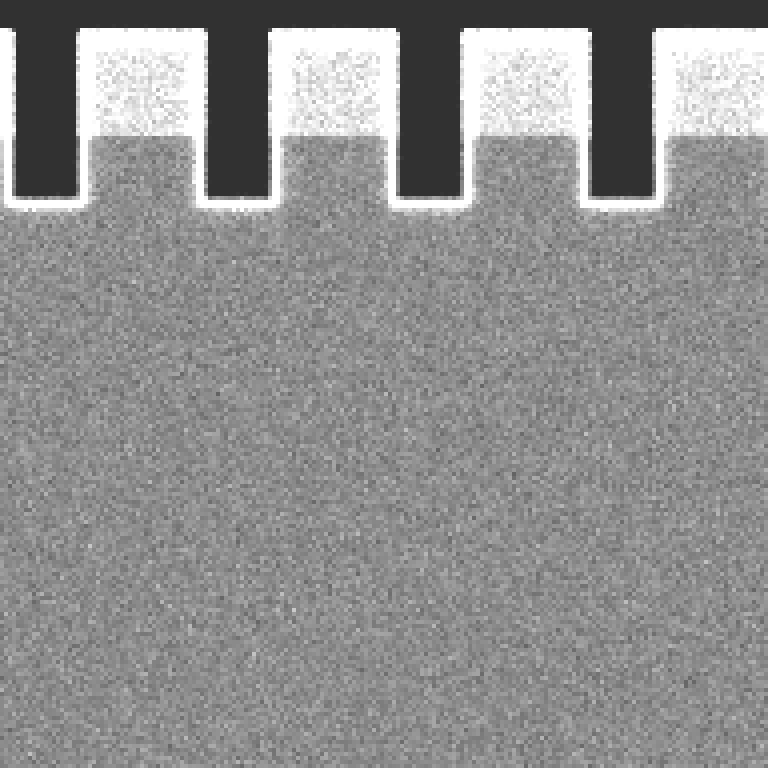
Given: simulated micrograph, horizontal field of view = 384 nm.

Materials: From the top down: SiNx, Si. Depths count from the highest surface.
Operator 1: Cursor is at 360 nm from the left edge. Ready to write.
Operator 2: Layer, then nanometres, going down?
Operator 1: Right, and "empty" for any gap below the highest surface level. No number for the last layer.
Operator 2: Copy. SiNx 52, Si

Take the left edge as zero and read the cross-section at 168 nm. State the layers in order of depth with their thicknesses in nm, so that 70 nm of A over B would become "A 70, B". SiNx 52, Si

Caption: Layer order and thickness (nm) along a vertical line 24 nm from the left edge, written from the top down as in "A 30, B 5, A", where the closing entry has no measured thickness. empty 84, Si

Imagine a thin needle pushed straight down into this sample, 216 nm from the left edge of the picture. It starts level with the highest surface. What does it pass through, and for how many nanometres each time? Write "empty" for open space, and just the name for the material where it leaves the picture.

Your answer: empty 84, Si